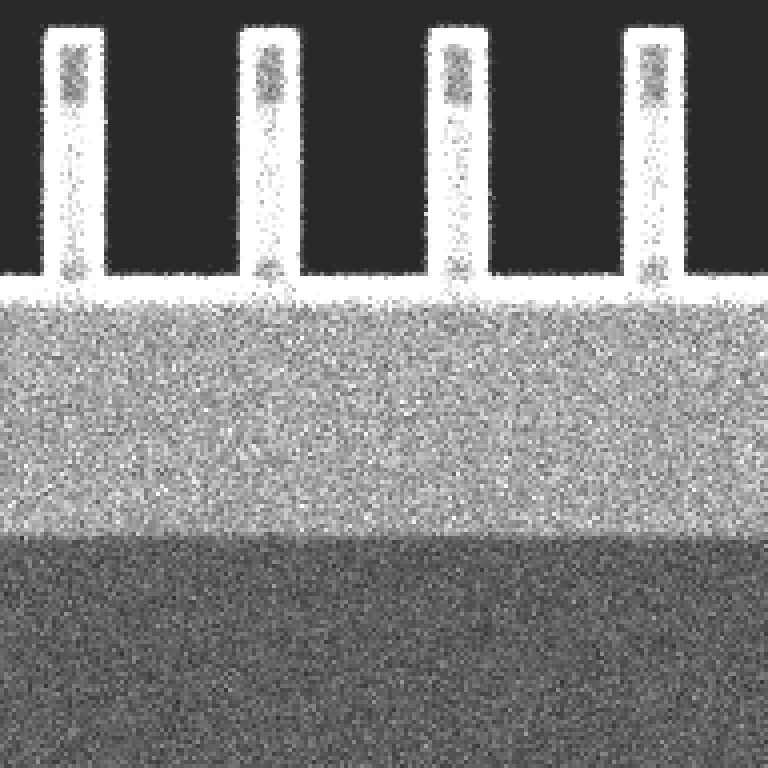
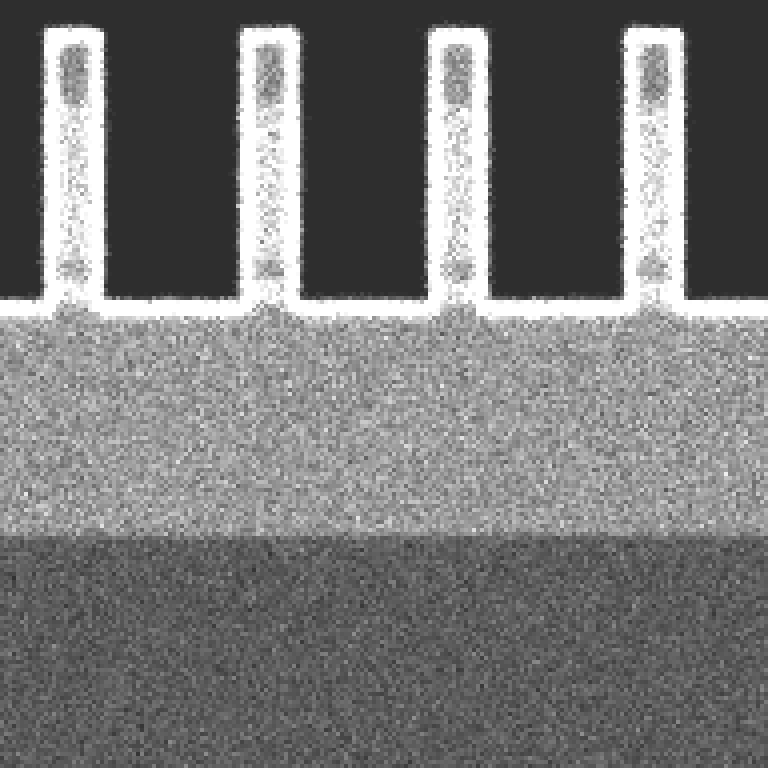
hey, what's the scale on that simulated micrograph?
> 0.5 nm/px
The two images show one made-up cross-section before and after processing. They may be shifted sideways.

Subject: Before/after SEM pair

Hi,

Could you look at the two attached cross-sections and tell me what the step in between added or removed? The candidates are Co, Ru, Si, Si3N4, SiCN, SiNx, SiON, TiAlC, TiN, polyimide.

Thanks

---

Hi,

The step removed Ru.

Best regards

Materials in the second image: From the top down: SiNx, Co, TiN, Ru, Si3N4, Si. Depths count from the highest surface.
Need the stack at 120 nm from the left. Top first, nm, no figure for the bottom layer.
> empty 136, Si3N4 116, Si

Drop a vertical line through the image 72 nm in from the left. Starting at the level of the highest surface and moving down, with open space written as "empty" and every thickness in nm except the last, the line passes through empty 136, Si3N4 116, Si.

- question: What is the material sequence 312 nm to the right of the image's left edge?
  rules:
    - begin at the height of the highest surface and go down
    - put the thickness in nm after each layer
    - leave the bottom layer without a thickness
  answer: empty 136, Si3N4 116, Si